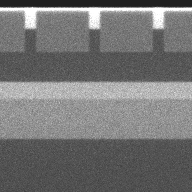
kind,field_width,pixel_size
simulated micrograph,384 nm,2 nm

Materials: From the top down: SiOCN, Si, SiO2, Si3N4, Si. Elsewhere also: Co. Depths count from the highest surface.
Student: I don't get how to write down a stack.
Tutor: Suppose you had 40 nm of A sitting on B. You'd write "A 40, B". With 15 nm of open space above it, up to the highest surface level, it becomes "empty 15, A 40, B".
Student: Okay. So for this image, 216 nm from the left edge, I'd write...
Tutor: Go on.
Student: SiOCN 88, Si 60, SiO2 34, Si3N4 80, Si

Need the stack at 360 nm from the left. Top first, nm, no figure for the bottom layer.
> SiOCN 88, Si 60, SiO2 34, Si3N4 80, Si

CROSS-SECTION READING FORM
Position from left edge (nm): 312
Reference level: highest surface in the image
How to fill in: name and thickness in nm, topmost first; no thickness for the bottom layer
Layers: Co 42, Si 106, SiO2 34, Si3N4 80, Si